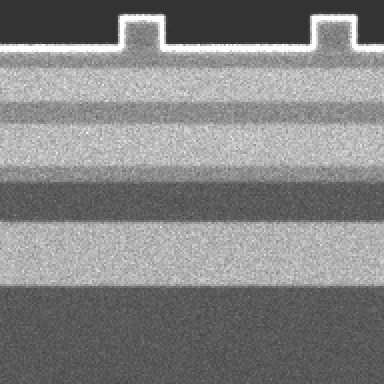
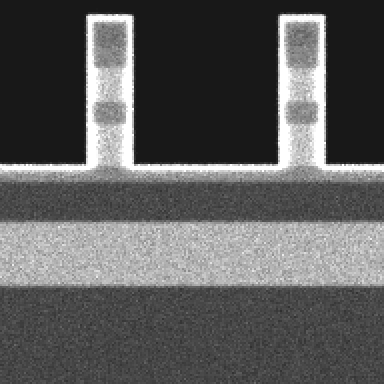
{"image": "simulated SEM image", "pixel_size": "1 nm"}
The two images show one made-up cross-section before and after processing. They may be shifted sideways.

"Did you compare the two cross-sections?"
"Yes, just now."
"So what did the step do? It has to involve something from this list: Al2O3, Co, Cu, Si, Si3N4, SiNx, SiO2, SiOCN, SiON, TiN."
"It removed Al2O3 and Si3N4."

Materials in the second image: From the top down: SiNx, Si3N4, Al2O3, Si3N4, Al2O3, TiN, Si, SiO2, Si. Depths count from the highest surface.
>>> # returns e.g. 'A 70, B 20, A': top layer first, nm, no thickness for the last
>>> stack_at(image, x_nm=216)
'empty 150, TiN 16, Si 40, SiO2 64, Si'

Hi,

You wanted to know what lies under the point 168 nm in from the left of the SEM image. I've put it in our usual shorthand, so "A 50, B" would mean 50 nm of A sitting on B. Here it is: empty 150, TiN 16, Si 40, SiO2 64, Si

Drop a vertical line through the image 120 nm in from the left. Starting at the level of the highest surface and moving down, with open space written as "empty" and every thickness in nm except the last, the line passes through SiNx 30, Si3N4 22, Al2O3 34, Si3N4 22, Al2O3 42, TiN 16, Si 40, SiO2 64, Si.